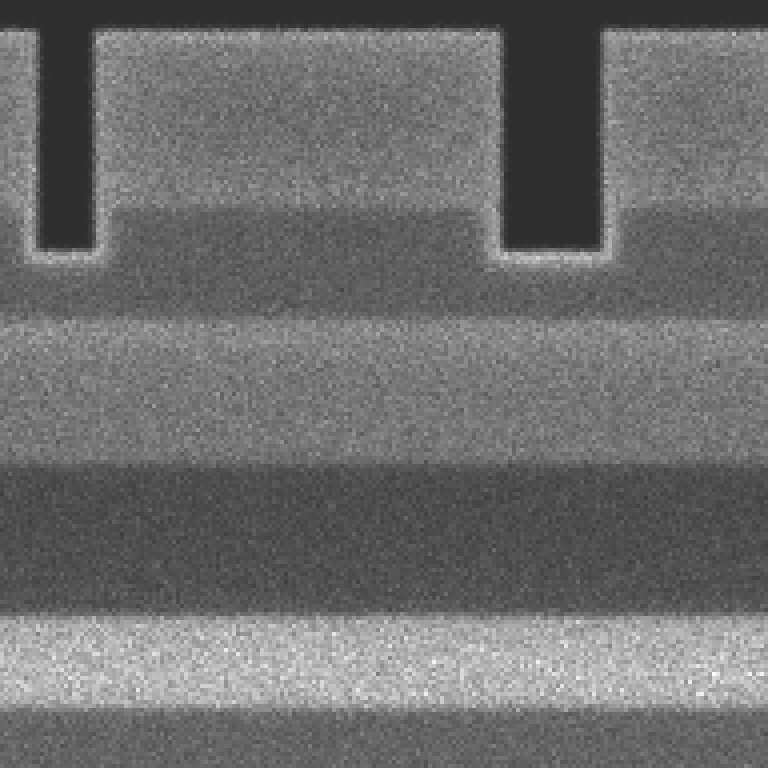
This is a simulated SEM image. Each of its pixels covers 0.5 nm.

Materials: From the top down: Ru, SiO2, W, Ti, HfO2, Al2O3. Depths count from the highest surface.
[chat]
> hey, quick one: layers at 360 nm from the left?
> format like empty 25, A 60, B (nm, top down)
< Ru 88, SiO2 56, W 72, Ti 76, HfO2 46, Al2O3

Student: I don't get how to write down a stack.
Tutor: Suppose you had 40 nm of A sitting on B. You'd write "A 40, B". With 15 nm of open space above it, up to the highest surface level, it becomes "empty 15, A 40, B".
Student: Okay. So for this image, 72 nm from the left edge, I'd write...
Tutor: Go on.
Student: Ru 88, SiO2 56, W 72, Ti 76, HfO2 46, Al2O3